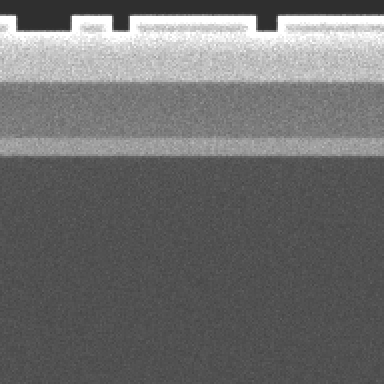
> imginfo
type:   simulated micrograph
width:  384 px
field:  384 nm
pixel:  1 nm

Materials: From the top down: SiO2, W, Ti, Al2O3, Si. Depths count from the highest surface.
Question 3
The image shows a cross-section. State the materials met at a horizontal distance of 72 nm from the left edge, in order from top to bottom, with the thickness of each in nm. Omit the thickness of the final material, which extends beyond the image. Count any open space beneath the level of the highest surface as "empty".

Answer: SiO2 16, W 50, Ti 56, Al2O3 18, Si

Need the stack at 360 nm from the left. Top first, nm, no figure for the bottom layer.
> SiO2 16, W 50, Ti 56, Al2O3 18, Si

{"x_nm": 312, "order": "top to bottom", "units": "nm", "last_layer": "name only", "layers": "SiO2 16, W 50, Ti 56, Al2O3 18, Si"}